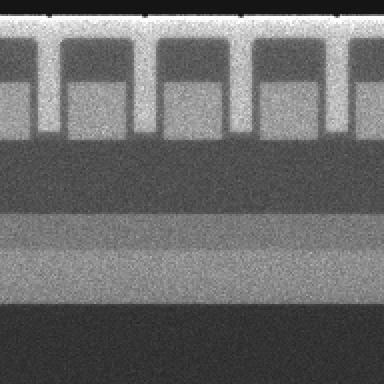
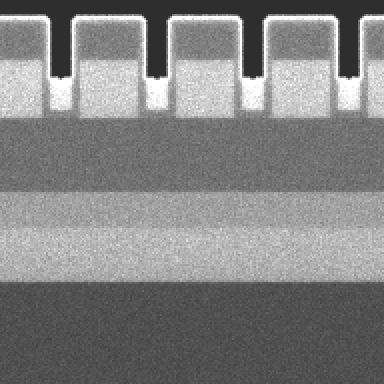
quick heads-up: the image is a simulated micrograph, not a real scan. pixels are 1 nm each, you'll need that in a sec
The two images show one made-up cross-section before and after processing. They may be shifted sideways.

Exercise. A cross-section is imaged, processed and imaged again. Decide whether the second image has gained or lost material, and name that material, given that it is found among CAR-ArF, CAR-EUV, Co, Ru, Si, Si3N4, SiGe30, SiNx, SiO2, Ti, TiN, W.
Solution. removed: W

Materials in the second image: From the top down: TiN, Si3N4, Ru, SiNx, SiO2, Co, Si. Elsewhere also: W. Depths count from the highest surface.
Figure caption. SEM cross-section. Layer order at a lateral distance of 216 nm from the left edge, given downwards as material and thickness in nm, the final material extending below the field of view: TiN 8, Si3N4 36, Ru 58, SiNx 74, SiO2 36, Co 54, Si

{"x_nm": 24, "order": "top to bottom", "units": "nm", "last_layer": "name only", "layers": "TiN 8, Si3N4 36, Ru 58, SiNx 74, SiO2 36, Co 54, Si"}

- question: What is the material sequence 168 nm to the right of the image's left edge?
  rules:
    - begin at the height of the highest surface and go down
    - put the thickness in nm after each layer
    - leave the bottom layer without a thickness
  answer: empty 4, TiN 98, SiNx 74, SiO2 36, Co 54, Si